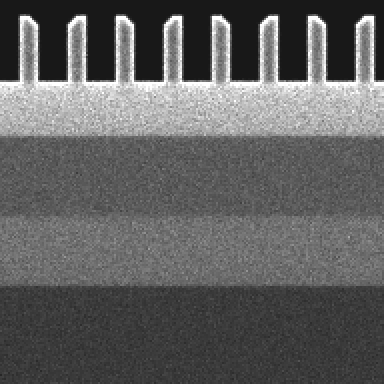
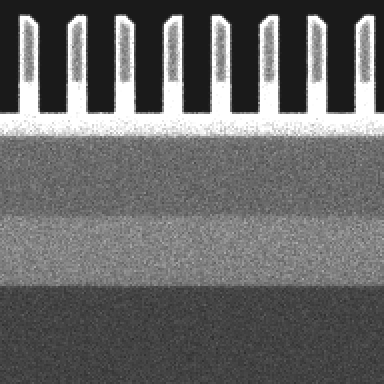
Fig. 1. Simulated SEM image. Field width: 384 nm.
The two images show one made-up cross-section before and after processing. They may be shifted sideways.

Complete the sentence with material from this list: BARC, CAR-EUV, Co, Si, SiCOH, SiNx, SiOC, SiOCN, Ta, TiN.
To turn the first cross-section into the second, Co must be removed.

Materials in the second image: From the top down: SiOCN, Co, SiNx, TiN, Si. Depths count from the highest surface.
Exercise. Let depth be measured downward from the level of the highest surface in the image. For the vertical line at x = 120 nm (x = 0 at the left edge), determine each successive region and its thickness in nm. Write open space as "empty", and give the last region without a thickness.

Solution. SiOCN 66, Co 54, SiNx 80, TiN 70, Si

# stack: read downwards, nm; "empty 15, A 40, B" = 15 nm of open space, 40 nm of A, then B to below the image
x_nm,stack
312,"SiOCN 66, Co 54, SiNx 80, TiN 70, Si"